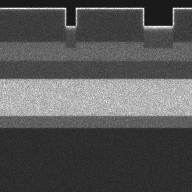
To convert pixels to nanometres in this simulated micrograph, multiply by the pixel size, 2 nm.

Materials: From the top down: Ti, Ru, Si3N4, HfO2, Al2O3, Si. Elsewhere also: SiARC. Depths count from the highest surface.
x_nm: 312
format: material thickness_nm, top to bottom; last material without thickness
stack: empty 36, SiARC 44, Ru 26, Si3N4 36, HfO2 74, Al2O3 24, Si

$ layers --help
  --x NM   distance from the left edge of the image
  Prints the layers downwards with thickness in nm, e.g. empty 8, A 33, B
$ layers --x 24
Ti 68, Ru 38, Si3N4 36, HfO2 74, Al2O3 24, Si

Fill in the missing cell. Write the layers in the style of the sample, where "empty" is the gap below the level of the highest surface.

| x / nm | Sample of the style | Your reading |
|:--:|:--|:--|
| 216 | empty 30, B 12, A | Ti 68, Ru 38, Si3N4 36, HfO2 74, Al2O3 24, Si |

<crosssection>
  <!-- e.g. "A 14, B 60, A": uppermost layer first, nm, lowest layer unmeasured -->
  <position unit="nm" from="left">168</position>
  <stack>Ti 68, Ru 38, Si3N4 36, HfO2 74, Al2O3 24, Si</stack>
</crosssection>